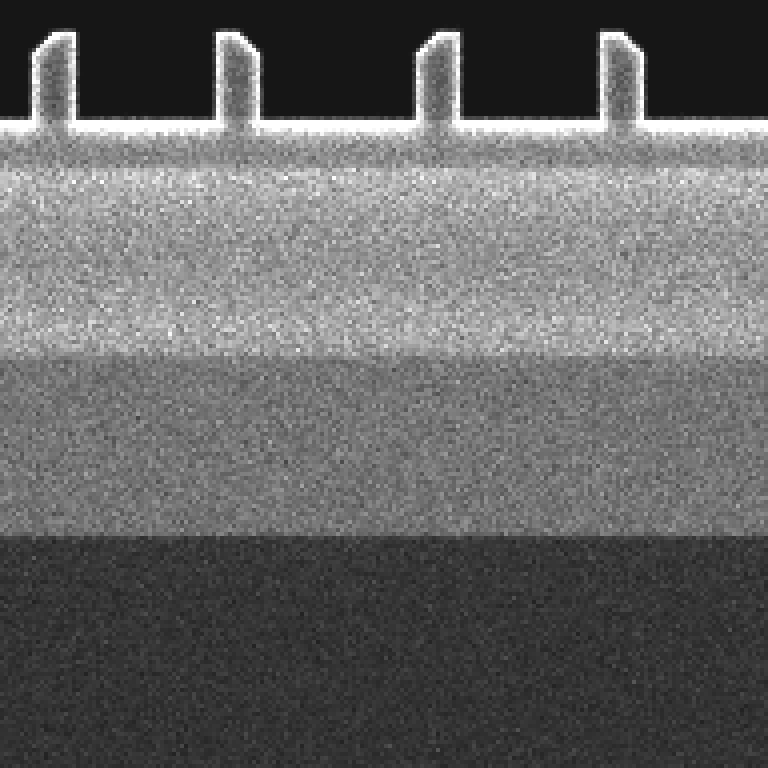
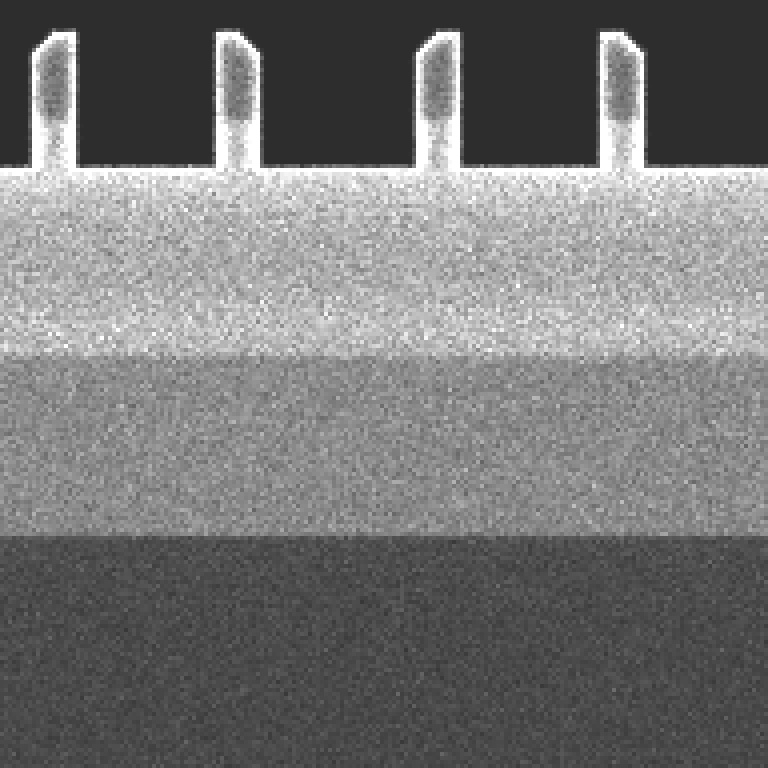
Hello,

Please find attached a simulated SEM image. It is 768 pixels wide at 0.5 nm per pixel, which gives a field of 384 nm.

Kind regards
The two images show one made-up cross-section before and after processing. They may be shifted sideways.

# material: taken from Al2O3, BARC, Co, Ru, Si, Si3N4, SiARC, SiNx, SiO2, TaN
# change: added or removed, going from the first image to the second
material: Al2O3
change: removed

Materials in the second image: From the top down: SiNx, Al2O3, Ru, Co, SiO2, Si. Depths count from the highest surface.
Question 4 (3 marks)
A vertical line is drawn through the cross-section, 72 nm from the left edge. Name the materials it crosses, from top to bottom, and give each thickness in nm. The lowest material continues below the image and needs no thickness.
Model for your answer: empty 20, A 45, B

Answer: empty 68, Ru 82, Co 12, SiO2 90, Si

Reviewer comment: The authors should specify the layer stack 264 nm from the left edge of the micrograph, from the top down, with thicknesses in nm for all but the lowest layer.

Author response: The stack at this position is empty 68, Ru 82, Co 12, SiO2 90, Si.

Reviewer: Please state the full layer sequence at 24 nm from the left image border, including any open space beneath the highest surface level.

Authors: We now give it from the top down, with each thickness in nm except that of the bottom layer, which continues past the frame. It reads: empty 2, SiNx 42, Al2O3 24, Ru 82, Co 12, SiO2 90, Si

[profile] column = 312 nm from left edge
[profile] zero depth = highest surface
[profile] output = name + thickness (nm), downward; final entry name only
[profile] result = empty 2, SiNx 42, Al2O3 24, Ru 82, Co 12, SiO2 90, Si